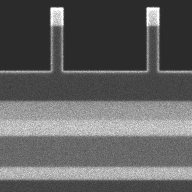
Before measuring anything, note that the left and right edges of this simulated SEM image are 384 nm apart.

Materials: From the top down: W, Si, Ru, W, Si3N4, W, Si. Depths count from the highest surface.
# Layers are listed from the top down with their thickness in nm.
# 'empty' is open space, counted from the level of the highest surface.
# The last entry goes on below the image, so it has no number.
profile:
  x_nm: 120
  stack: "W 36, Si 150, Ru 38, W 32, Si3N4 62, W 26, Si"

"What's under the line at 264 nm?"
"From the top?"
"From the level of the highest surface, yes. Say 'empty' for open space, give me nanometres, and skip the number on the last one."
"empty 126, Si 60, Ru 38, W 32, Si3N4 62, W 26, Si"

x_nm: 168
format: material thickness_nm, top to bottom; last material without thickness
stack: empty 126, Si 60, Ru 38, W 32, Si3N4 62, W 26, Si